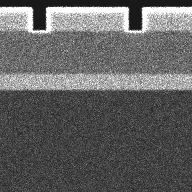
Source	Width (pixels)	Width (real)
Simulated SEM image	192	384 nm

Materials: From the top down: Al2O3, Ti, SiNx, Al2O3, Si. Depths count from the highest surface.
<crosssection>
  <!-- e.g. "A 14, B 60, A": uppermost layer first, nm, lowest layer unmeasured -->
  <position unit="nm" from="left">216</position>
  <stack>Al2O3 46, Ti 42, SiNx 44, Al2O3 32, Si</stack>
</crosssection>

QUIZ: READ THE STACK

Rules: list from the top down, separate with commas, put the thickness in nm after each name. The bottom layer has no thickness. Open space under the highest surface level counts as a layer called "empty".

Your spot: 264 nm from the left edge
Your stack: empty 46, Ti 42, SiNx 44, Al2O3 32, Si